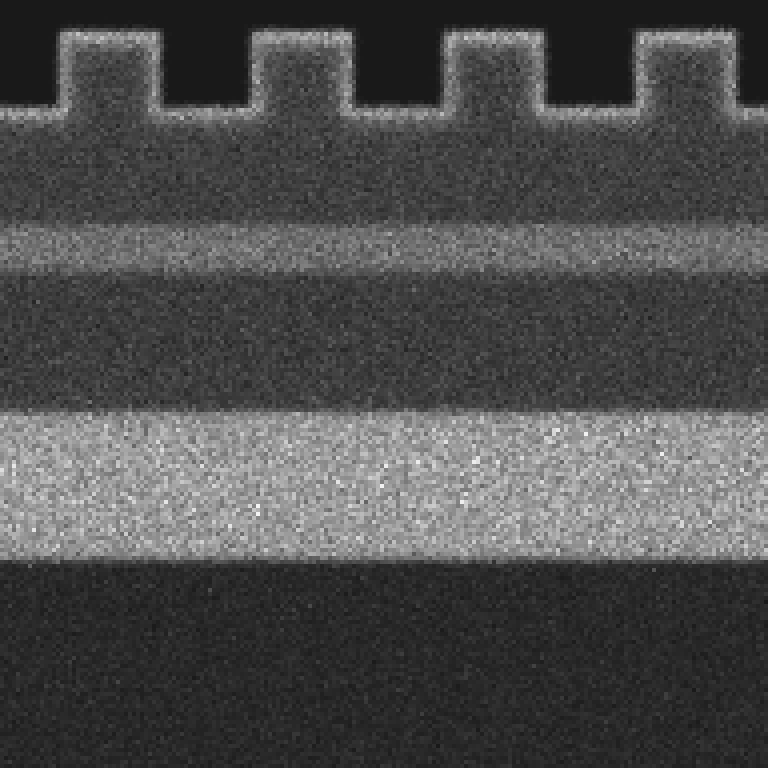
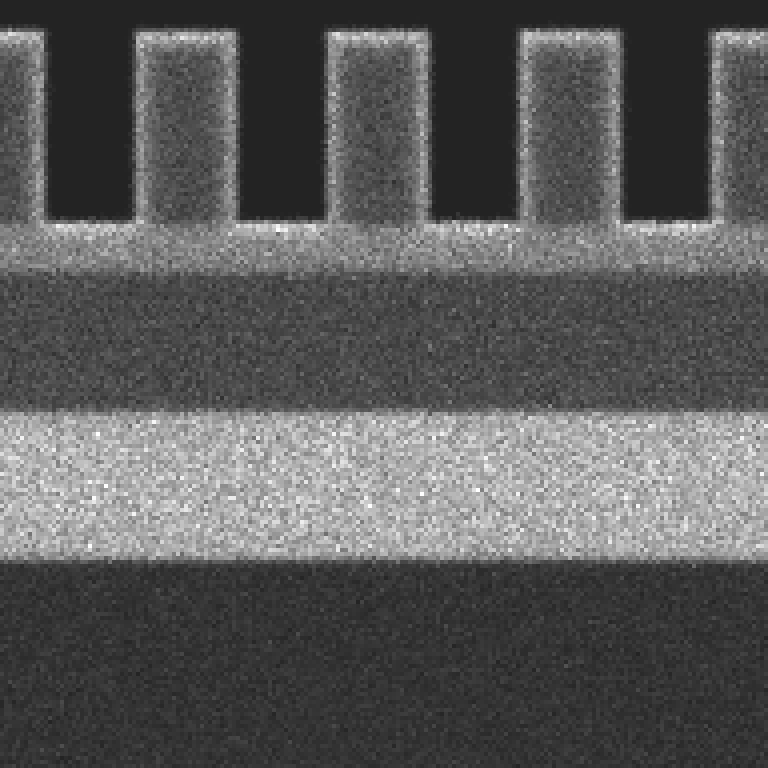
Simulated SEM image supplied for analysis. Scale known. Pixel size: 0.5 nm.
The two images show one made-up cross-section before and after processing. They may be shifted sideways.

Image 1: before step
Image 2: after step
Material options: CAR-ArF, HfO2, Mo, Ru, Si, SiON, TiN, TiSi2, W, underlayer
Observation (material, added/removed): underlayer, removed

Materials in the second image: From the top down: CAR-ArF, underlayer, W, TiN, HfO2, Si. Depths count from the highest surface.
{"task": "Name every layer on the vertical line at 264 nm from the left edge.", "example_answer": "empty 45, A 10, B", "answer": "CAR-ArF 38, underlayer 58, W 24, TiN 70, HfO2 74, Si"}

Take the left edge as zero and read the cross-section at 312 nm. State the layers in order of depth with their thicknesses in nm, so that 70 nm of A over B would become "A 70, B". empty 96, W 24, TiN 70, HfO2 74, Si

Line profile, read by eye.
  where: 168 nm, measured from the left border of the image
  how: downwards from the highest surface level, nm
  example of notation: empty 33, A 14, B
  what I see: CAR-ArF 38, underlayer 58, W 24, TiN 70, HfO2 74, Si